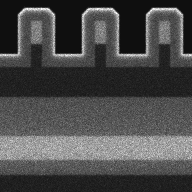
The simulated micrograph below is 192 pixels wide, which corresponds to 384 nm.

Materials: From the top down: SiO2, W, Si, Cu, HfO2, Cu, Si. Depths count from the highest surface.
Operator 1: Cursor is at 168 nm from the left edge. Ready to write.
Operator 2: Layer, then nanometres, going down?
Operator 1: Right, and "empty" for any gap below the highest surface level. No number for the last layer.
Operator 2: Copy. empty 8, SiO2 110, Si 60, Cu 78, HfO2 48, Cu 30, Si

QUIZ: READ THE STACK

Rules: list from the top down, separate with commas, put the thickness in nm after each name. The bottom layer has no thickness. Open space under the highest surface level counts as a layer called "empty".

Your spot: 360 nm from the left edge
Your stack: empty 8, SiO2 110, Si 60, Cu 78, HfO2 48, Cu 30, Si